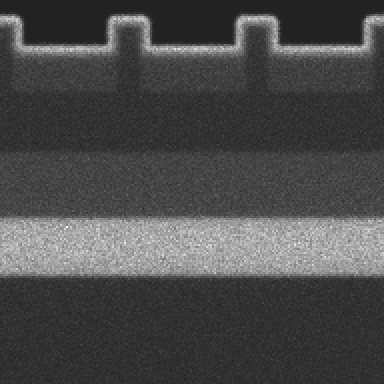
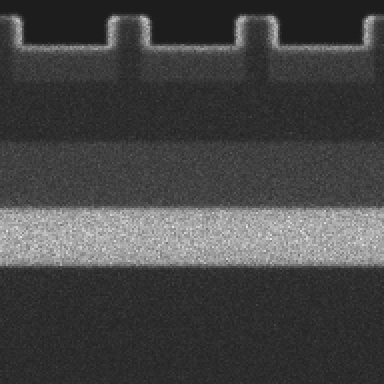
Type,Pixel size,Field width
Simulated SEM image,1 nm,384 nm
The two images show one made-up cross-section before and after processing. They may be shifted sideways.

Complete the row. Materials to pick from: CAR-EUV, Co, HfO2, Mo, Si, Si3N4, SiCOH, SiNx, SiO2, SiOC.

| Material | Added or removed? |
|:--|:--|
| SiO2 | removed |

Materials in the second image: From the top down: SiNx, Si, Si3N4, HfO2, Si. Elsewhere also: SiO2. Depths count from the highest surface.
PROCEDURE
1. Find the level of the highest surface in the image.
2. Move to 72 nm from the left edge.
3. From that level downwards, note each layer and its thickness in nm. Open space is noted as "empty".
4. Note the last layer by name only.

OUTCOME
empty 30, SiNx 36, Si 60, Si3N4 66, HfO2 58, Si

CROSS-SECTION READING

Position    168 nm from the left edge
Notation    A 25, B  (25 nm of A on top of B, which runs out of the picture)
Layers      empty 30, SiNx 36, Si 60, Si3N4 66, HfO2 58, Si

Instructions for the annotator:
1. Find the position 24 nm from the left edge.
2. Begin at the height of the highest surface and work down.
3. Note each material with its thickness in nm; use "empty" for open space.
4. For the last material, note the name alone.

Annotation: empty 30, SiNx 36, Si 60, Si3N4 66, HfO2 58, Si